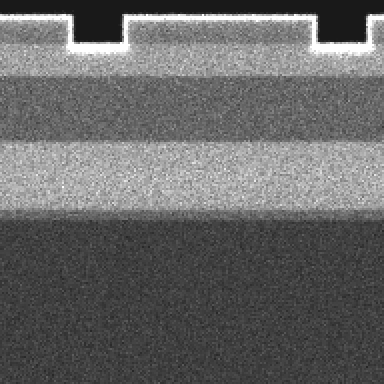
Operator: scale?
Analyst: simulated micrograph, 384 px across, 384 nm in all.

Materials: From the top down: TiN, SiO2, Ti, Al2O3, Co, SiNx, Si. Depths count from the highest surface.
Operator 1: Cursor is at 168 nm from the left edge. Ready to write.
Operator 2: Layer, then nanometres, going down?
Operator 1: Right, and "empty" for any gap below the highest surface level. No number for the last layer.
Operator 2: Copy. TiN 28, SiO2 32, Ti 66, Al2O3 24, Co 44, SiNx 10, Si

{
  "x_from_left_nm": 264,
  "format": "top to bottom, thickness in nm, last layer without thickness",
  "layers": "TiN 28, SiO2 32, Ti 66, Al2O3 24, Co 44, SiNx 10, Si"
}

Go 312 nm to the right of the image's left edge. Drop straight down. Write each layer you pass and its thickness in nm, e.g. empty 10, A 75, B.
TiN 28, SiO2 32, Ti 66, Al2O3 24, Co 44, SiNx 10, Si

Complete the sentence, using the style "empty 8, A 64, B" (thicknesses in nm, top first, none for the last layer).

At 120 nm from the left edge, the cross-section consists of empty 28, SiO2 32, Ti 66, Al2O3 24, Co 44, SiNx 10, Si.